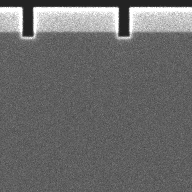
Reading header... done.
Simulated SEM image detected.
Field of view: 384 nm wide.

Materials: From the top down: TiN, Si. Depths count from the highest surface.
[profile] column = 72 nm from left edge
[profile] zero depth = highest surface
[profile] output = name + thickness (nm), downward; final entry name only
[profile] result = TiN 48, Si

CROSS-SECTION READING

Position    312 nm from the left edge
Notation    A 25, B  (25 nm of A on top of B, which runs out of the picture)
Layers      TiN 48, Si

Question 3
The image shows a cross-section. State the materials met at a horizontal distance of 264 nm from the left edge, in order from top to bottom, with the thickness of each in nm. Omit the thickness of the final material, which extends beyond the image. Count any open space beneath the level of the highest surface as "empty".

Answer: TiN 48, Si